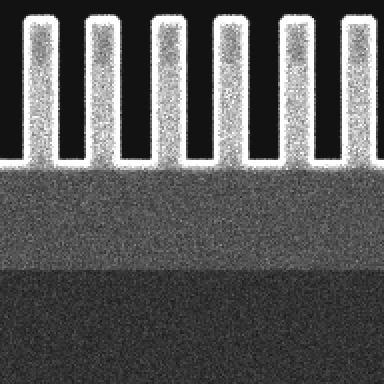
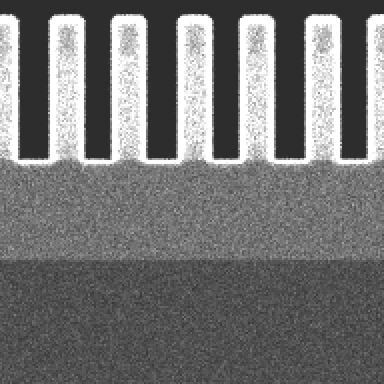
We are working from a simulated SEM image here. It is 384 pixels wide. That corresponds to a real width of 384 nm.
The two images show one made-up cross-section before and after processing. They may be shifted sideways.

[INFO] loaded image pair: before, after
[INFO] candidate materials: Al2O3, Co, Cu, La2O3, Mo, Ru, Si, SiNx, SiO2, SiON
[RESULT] removed SiO2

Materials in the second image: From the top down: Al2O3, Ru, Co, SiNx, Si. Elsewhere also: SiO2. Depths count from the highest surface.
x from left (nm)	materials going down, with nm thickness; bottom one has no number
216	empty 144, SiNx 100, Si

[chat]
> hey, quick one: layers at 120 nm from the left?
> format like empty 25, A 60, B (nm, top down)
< SiO2 144, SiNx 100, Si